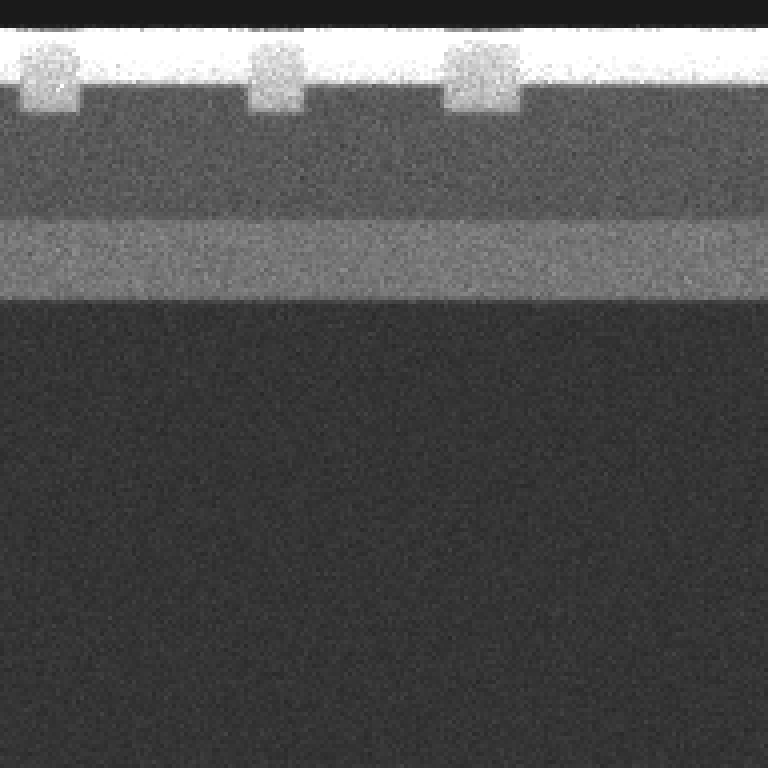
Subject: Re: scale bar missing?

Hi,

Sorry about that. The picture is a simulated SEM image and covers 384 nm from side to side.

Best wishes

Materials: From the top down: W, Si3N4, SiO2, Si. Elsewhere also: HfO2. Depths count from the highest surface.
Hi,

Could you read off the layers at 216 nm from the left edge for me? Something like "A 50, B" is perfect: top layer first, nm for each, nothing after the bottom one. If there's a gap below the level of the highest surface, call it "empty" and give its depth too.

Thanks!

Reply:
HfO2 26, Si3N4 68, SiO2 40, Si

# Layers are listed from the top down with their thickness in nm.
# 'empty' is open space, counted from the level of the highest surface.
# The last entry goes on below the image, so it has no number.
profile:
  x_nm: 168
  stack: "HfO2 26, Si3N4 68, SiO2 40, Si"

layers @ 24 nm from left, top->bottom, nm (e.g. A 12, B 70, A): W 40, Si3N4 54, SiO2 40, Si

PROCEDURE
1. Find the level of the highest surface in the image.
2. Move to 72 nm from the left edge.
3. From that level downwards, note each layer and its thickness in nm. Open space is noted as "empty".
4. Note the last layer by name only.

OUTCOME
HfO2 26, Si3N4 68, SiO2 40, Si